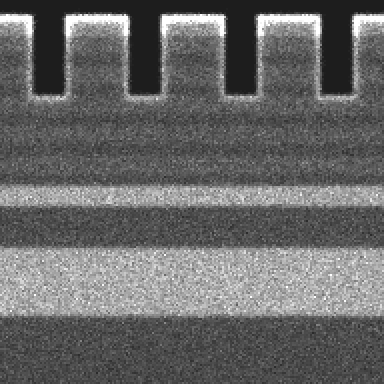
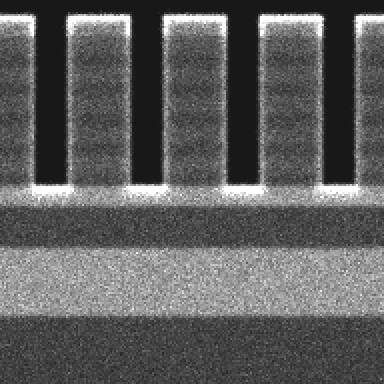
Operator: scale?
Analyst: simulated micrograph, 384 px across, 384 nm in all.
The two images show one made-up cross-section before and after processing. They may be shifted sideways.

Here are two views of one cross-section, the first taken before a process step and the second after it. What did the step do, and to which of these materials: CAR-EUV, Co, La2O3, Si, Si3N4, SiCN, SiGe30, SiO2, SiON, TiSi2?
It removed Si and SiGe30.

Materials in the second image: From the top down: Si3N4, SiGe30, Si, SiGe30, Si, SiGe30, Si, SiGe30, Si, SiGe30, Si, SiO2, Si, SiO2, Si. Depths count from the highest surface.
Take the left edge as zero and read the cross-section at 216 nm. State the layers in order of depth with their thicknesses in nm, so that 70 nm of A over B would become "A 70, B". Si3N4 20, SiGe30 18, Si 12, SiGe30 18, Si 12, SiGe30 18, Si 12, SiGe30 18, Si 12, SiGe30 18, Si 12, SiO2 20, Si 42, SiO2 68, Si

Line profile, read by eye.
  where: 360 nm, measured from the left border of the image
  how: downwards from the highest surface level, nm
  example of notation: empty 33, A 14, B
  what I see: Si3N4 20, SiGe30 18, Si 12, SiGe30 18, Si 12, SiGe30 18, Si 12, SiGe30 18, Si 12, SiGe30 18, Si 12, SiO2 20, Si 42, SiO2 68, Si